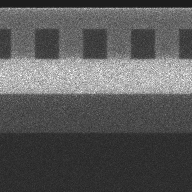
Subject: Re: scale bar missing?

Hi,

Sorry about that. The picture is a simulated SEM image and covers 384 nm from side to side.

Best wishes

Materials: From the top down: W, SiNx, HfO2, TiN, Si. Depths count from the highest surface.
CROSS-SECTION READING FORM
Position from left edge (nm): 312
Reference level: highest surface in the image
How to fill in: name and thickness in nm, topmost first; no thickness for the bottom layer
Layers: W 102, HfO2 70, TiN 78, Si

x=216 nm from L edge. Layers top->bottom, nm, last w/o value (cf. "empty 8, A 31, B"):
W 102, HfO2 70, TiN 78, Si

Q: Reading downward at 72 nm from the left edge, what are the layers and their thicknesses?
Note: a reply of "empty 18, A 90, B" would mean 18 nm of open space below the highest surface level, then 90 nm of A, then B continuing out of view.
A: W 42, SiNx 60, HfO2 70, TiN 78, Si